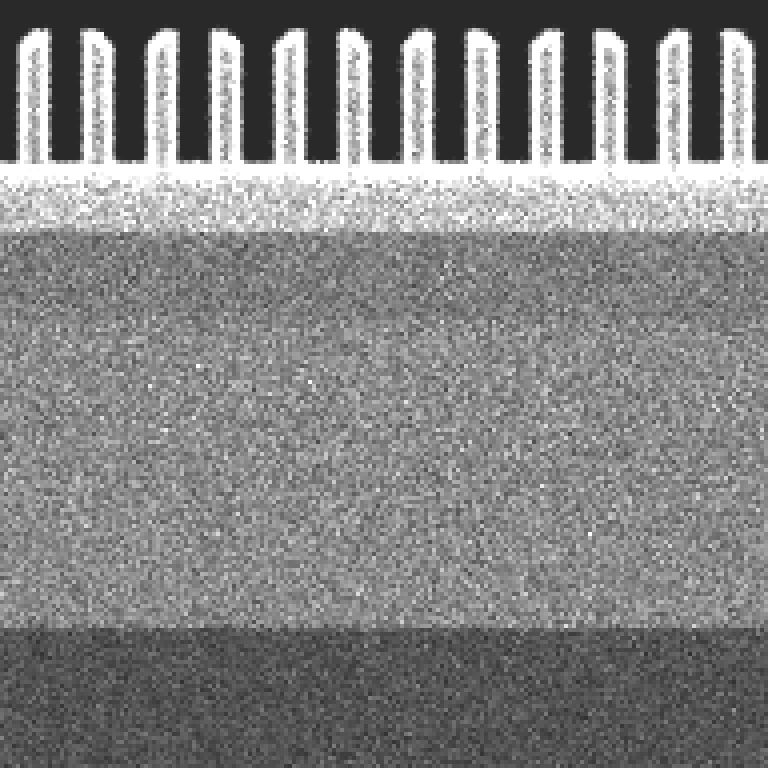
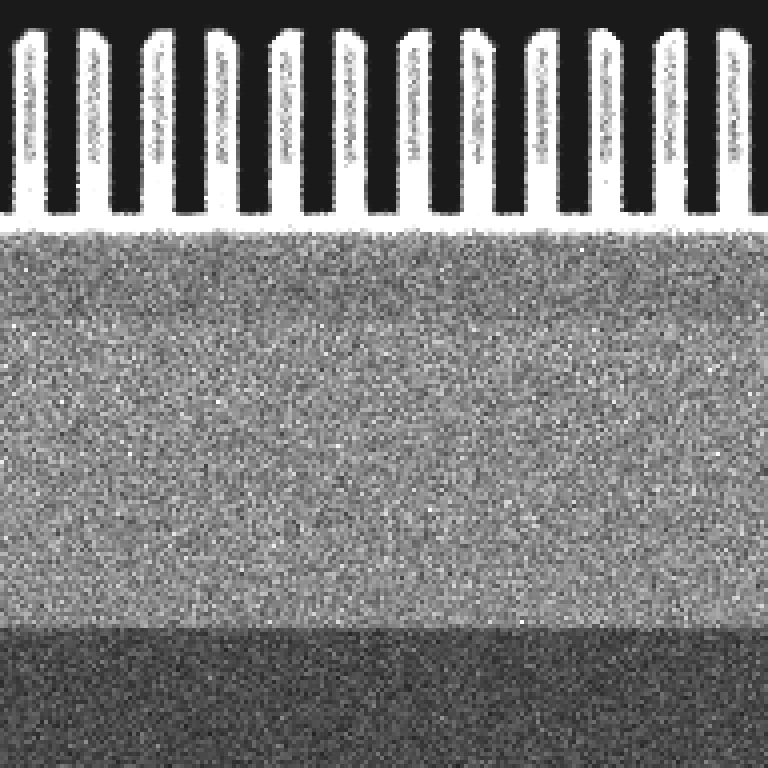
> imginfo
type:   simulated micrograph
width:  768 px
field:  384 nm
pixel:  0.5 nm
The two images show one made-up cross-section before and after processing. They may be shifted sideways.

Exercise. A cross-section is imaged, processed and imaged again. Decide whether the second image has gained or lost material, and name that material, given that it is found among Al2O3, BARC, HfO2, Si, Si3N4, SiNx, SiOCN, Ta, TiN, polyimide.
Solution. removed: Al2O3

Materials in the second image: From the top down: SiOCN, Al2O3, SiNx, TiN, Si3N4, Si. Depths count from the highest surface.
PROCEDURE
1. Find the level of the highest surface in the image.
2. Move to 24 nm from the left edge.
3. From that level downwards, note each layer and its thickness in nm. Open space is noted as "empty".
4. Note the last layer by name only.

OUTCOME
empty 92, Al2O3 8, SiNx 44, TiN 84, Si3N4 70, Si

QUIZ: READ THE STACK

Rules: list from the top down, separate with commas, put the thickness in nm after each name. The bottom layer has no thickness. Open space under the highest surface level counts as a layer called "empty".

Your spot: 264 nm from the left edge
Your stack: empty 6, SiOCN 60, Al2O3 34, SiNx 44, TiN 84, Si3N4 70, Si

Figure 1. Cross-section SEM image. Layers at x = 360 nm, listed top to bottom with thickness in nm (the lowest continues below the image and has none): SiOCN 66, Al2O3 34, SiNx 44, TiN 84, Si3N4 70, Si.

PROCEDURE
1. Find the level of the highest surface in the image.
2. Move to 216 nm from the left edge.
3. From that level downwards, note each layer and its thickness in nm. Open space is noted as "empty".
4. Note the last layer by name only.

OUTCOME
empty 92, Al2O3 8, SiNx 44, TiN 84, Si3N4 70, Si